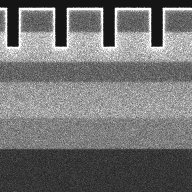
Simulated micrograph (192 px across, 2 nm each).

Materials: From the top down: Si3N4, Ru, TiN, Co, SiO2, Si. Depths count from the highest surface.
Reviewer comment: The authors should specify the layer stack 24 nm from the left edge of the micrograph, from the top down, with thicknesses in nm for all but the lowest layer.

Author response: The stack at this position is empty 78, Ru 30, TiN 40, Co 72, SiO2 62, Si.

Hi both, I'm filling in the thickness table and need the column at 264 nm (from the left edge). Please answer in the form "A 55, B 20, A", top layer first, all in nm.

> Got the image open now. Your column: Si3N4 48, Ru 60, TiN 40, Co 72, SiO2 62, Si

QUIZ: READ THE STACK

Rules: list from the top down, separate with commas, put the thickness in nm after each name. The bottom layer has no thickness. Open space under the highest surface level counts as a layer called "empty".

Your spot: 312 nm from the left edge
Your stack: empty 78, Ru 30, TiN 40, Co 72, SiO2 62, Si